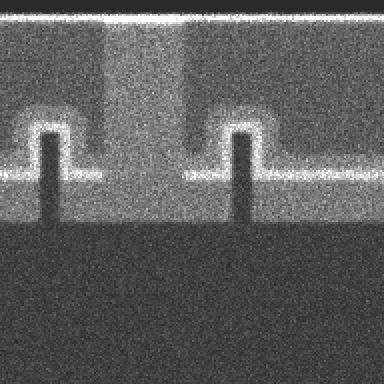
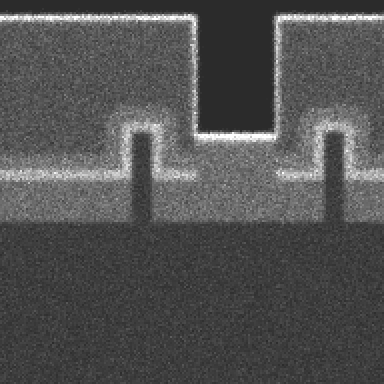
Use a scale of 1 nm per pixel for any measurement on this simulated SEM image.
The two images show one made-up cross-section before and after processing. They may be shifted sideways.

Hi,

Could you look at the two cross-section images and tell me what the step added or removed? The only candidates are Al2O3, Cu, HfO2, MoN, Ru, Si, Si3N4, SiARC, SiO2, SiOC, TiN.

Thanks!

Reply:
removed Al2O3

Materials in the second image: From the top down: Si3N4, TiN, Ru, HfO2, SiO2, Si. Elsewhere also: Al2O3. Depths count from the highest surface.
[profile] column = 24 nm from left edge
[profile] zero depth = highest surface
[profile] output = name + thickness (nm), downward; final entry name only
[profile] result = Si3N4 42, TiN 96, Ru 16, HfO2 10, SiO2 42, Si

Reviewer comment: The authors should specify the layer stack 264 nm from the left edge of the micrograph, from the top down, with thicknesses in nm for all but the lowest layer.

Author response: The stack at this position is empty 118, Al2O3 46, SiO2 42, Si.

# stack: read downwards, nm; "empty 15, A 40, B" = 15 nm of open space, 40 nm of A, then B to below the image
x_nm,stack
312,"Si3N4 42, TiN 48, Ru 64, HfO2 10, SiO2 42, Si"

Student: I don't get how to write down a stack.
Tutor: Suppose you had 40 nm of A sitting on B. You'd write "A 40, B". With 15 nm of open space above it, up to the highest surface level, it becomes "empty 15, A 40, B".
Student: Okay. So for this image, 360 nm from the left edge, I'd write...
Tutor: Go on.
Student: Si3N4 42, TiN 52, Ru 60, HfO2 10, SiO2 42, Si